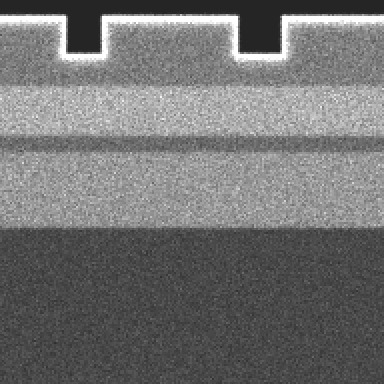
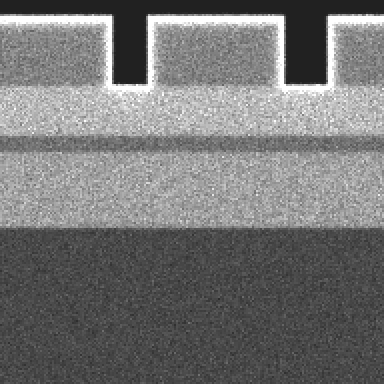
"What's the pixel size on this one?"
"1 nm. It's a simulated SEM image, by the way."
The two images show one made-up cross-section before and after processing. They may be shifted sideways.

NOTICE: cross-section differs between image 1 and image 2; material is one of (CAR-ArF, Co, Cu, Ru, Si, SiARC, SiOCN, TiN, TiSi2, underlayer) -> removed: underlayer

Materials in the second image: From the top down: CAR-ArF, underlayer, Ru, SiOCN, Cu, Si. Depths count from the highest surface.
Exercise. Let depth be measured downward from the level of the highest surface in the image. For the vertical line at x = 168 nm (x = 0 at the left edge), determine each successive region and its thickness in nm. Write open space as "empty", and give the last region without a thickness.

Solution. CAR-ArF 38, underlayer 32, Ru 50, SiOCN 16, Cu 76, Si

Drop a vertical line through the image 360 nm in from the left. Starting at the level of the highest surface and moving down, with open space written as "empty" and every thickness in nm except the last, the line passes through CAR-ArF 38, underlayer 32, Ru 50, SiOCN 16, Cu 76, Si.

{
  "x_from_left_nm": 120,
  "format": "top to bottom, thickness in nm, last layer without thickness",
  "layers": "empty 70, Ru 50, SiOCN 16, Cu 76, Si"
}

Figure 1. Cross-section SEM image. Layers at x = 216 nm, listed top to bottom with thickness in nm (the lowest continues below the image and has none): CAR-ArF 38, underlayer 32, Ru 50, SiOCN 16, Cu 76, Si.